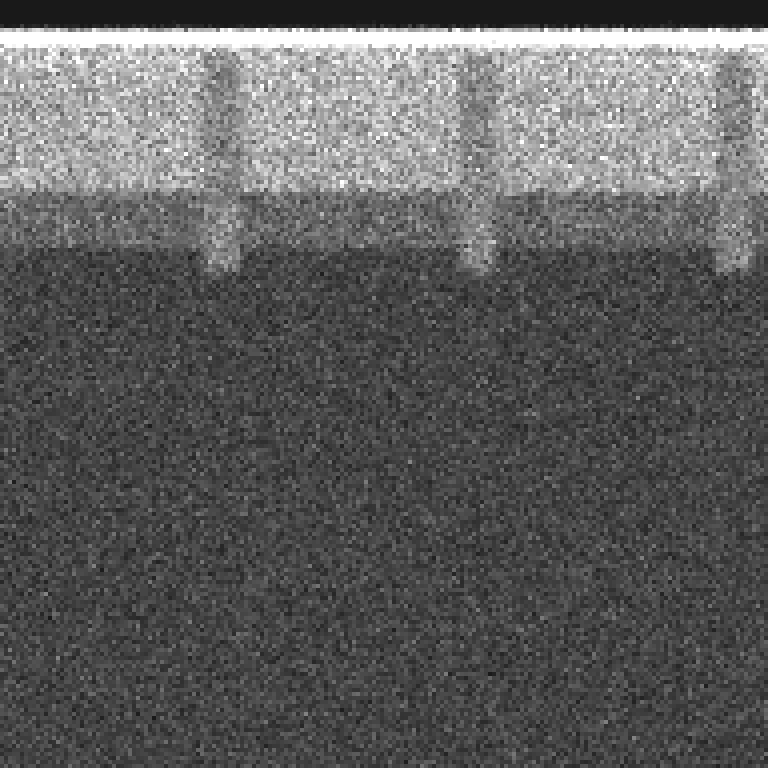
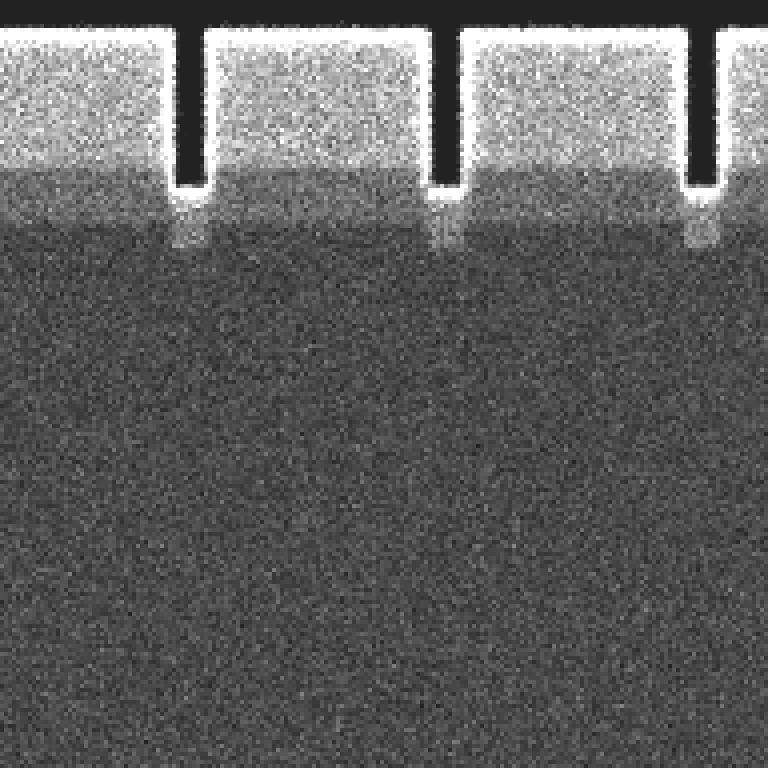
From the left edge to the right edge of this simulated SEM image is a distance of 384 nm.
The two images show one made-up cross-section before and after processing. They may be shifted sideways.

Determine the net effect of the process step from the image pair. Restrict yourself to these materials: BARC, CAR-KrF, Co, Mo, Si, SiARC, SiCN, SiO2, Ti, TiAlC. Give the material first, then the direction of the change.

SiARC: removed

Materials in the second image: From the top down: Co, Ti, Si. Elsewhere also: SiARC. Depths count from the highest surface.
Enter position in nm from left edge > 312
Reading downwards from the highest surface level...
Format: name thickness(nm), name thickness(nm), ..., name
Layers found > Co 68, Ti 28, Si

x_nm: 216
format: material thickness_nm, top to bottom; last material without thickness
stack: empty 78, SiARC 30, Si